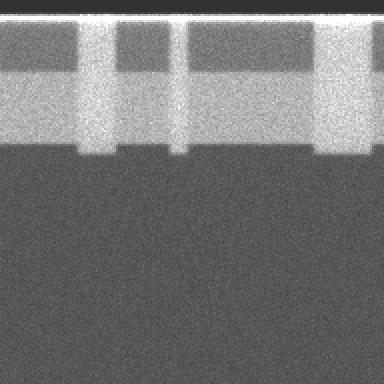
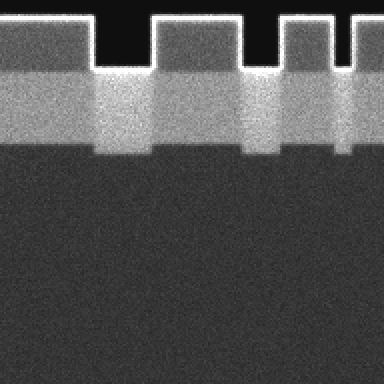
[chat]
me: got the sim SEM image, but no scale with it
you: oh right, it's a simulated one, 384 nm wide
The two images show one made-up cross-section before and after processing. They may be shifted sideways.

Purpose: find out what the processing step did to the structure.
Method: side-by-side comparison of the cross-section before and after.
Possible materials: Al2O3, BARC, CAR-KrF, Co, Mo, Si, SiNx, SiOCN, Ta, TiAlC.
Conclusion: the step removed Co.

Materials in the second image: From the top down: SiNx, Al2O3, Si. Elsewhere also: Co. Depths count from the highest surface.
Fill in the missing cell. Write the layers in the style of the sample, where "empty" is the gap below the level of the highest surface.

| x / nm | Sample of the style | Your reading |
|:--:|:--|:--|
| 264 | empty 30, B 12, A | empty 52, Co 86, Si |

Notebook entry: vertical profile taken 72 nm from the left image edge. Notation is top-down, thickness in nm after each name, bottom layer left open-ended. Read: SiNx 56, Al2O3 72, Si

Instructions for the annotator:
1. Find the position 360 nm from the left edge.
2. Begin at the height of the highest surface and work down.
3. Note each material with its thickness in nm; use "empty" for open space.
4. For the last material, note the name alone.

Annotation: SiNx 56, Al2O3 72, Si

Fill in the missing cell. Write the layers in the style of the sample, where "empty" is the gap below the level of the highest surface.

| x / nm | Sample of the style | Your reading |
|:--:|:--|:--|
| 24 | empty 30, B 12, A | SiNx 56, Al2O3 72, Si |